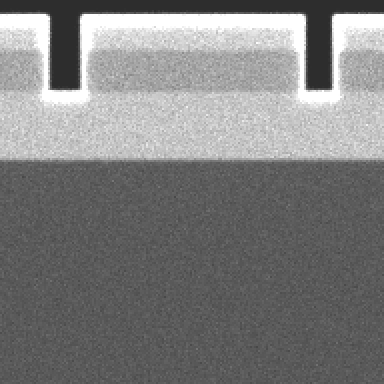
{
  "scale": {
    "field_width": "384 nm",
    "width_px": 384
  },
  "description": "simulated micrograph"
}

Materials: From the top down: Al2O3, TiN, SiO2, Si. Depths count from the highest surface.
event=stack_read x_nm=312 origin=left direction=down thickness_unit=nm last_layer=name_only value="empty 76, SiO2 68, Si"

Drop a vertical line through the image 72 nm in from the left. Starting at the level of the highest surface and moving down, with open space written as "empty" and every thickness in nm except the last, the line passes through empty 76, SiO2 68, Si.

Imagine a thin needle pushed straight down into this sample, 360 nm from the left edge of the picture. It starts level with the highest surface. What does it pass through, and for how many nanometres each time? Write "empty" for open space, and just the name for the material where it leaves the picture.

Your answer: Al2O3 34, TiN 42, SiO2 68, Si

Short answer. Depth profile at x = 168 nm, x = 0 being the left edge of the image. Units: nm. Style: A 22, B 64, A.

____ Al2O3 34, TiN 42, SiO2 68, Si